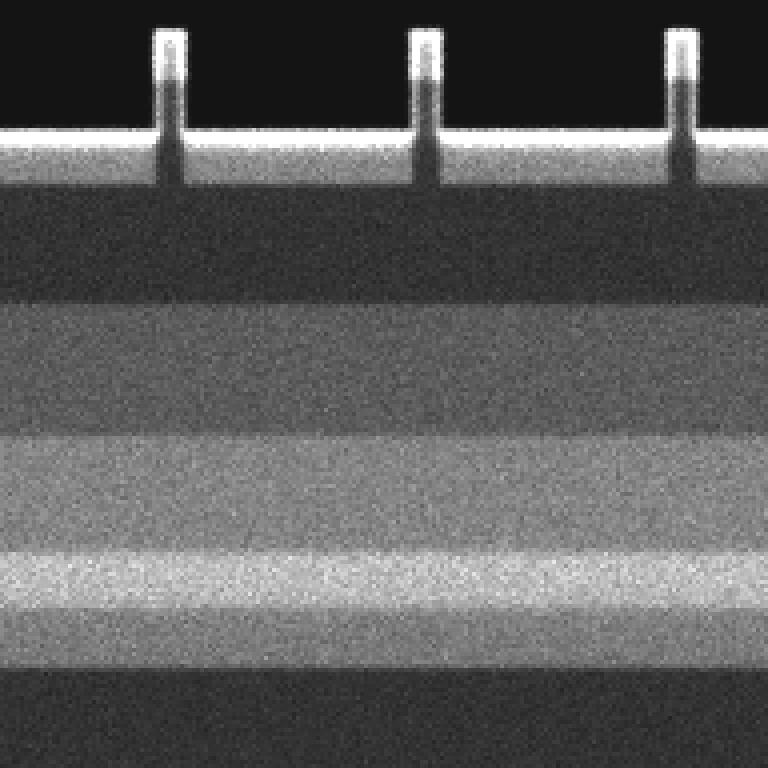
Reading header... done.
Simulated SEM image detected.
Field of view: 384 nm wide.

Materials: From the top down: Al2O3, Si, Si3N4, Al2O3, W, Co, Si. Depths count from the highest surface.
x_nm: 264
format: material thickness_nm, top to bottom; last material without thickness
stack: empty 50, Al2O3 26, Si 60, Si3N4 66, Al2O3 58, W 28, Co 30, Si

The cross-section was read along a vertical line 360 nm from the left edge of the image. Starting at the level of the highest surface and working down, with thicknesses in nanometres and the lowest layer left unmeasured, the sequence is empty 50, Al2O3 26, Si 60, Si3N4 66, Al2O3 58, W 28, Co 30, Si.